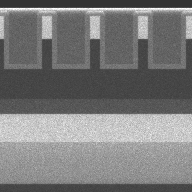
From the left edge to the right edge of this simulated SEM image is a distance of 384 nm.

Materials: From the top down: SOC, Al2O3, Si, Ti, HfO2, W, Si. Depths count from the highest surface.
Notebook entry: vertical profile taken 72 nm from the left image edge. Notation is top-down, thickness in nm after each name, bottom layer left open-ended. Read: SOC 112, Al2O3 10, Si 60, Ti 30, HfO2 56, W 84, Si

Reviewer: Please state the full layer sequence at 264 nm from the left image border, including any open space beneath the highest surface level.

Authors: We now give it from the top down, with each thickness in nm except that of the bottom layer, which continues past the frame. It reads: SOC 112, Al2O3 10, Si 60, Ti 30, HfO2 56, W 84, Si